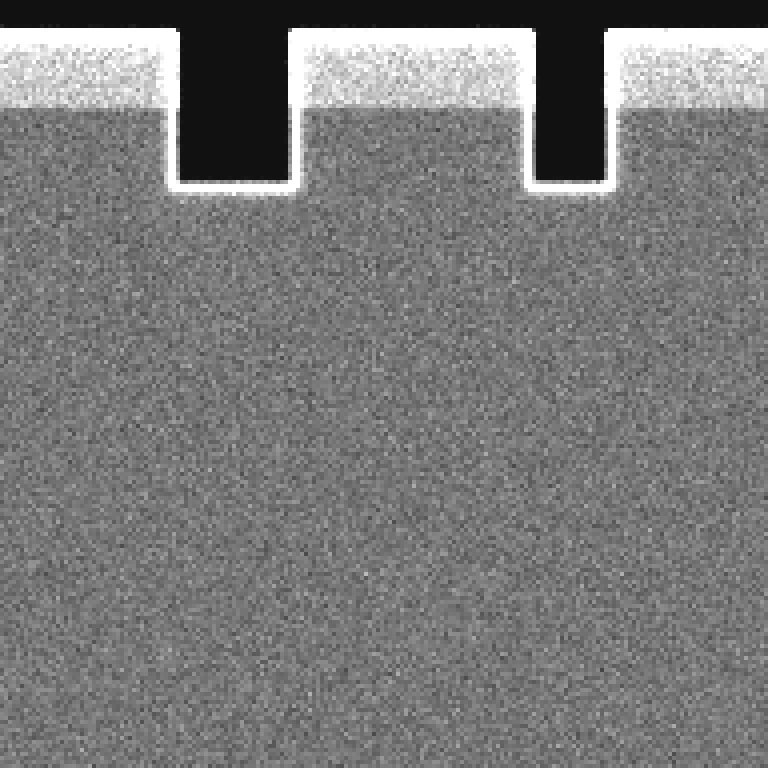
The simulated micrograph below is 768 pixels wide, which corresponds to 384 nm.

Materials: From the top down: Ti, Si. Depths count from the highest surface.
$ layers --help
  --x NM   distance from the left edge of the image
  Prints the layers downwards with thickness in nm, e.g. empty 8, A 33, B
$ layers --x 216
Ti 38, Si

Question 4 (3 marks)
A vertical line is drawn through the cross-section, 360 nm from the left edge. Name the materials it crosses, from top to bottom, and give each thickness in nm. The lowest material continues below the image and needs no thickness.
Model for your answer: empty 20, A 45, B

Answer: Ti 38, Si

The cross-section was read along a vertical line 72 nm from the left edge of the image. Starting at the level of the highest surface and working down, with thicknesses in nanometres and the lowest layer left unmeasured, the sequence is Ti 38, Si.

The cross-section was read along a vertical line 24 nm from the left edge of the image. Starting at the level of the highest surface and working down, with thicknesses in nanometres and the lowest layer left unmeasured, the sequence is Ti 38, Si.